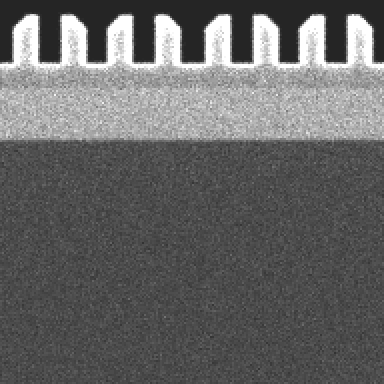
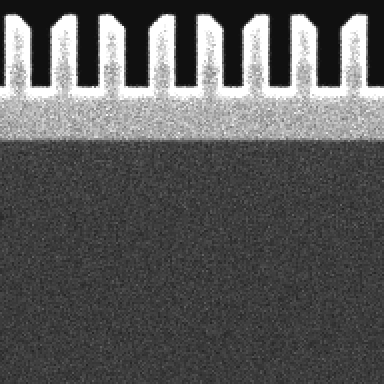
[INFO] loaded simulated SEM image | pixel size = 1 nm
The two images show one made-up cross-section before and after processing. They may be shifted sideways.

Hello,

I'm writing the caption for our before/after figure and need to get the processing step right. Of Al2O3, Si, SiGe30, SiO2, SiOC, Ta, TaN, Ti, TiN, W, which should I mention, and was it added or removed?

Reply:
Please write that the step removed TiN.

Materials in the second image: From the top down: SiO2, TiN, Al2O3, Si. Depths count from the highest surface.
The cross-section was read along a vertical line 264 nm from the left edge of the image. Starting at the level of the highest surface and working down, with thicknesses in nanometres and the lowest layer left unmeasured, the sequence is SiO2 48, TiN 24, Al2O3 52, Si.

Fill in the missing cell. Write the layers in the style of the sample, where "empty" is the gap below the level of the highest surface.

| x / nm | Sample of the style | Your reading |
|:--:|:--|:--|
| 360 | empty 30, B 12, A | SiO2 48, TiN 24, Al2O3 52, Si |